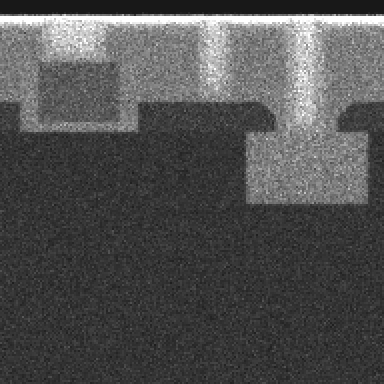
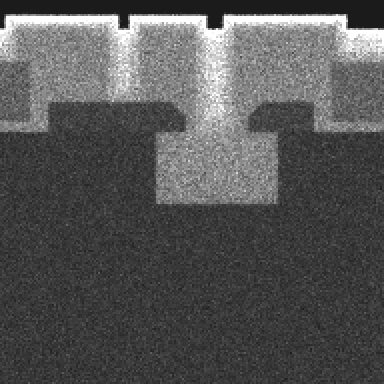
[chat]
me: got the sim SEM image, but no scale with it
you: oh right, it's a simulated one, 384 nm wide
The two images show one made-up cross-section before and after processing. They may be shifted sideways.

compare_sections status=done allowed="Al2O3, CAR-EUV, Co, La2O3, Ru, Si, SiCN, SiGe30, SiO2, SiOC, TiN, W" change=removed material="W"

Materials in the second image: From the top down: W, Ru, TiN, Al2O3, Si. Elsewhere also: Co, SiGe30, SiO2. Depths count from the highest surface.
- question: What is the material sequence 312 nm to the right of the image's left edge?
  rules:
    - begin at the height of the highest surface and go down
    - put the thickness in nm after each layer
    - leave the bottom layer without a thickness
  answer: SiO2 86, SiGe30 30, Si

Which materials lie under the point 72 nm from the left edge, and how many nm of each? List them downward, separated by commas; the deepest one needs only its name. SiO2 86, SiGe30 30, Si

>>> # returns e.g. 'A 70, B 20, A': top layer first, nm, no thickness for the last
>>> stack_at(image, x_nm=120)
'empty 14, W 62, Ru 10, SiGe30 30, Si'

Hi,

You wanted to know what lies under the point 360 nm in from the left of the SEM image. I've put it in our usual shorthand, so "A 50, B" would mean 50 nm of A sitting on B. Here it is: empty 14, W 22, Ru 10, TiN 60, Al2O3 10, Si